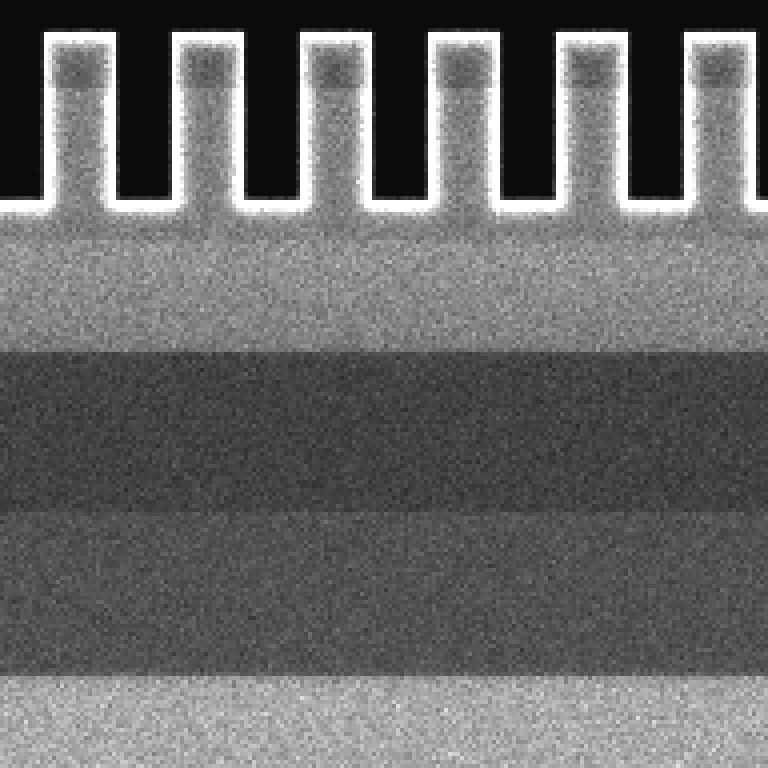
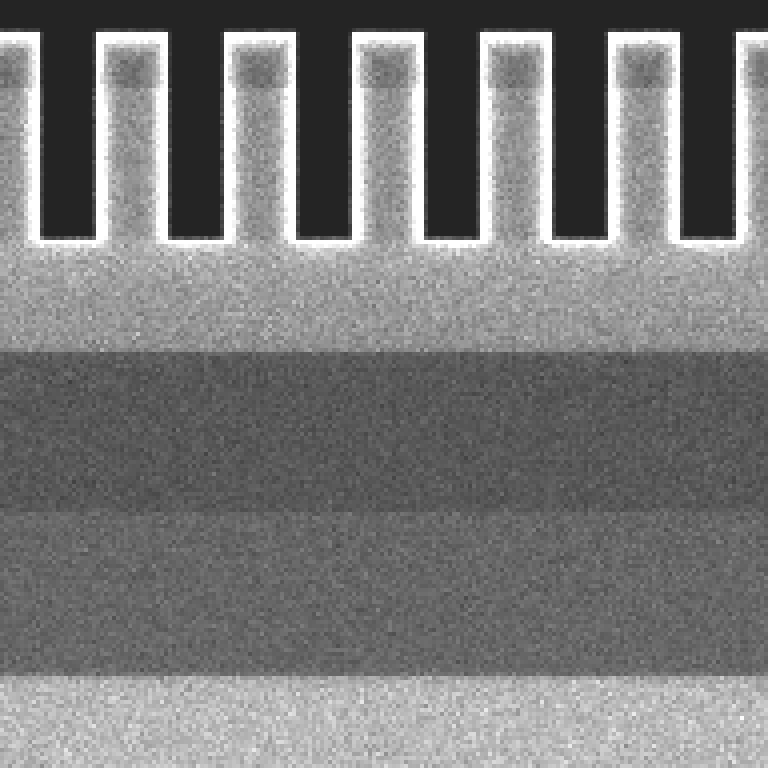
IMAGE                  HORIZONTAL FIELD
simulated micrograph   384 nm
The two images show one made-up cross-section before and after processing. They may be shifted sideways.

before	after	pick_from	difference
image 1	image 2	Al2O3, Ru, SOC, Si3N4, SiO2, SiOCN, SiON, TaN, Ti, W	Al2O3 removed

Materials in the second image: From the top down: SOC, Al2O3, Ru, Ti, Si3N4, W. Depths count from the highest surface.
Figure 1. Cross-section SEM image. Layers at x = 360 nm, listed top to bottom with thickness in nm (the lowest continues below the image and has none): empty 104, Ru 56, Ti 80, Si3N4 82, W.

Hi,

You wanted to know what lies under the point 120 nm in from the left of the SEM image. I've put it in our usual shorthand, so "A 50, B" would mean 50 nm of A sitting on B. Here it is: SOC 28, Al2O3 76, Ru 56, Ti 80, Si3N4 82, W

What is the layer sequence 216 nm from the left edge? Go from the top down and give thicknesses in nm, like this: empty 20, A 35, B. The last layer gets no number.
empty 104, Ru 56, Ti 80, Si3N4 82, W